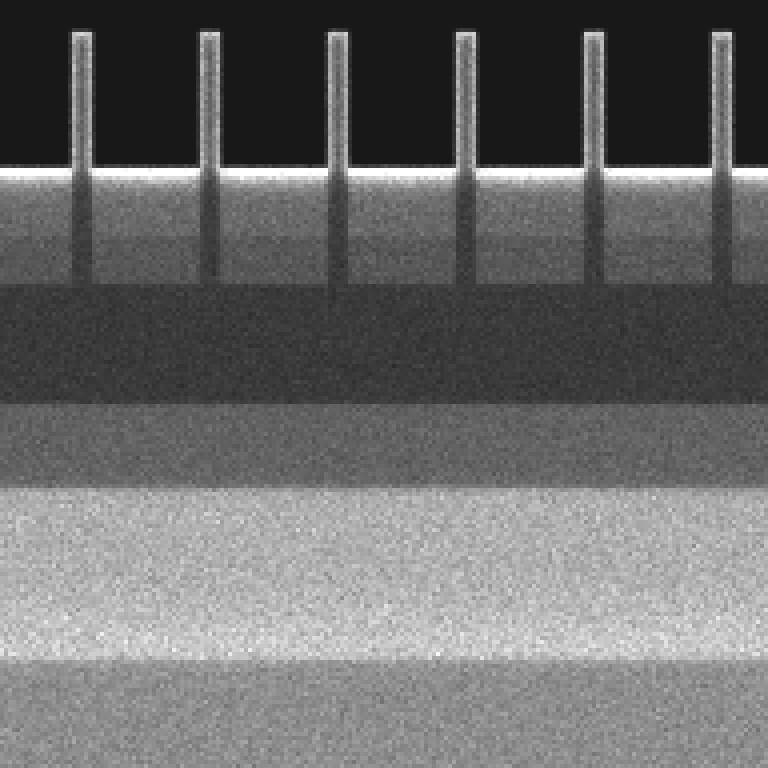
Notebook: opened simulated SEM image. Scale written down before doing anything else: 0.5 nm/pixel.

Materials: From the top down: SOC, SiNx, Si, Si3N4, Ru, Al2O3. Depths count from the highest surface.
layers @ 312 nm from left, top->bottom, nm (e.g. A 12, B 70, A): empty 68, SOC 34, SiNx 24, Si 60, Si3N4 42, Ru 86, Al2O3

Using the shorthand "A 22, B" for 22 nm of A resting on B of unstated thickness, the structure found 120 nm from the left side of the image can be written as empty 68, SOC 34, SiNx 24, Si 60, Si3N4 42, Ru 86, Al2O3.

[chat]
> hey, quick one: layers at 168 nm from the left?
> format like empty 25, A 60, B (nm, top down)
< Si 186, Si3N4 42, Ru 86, Al2O3